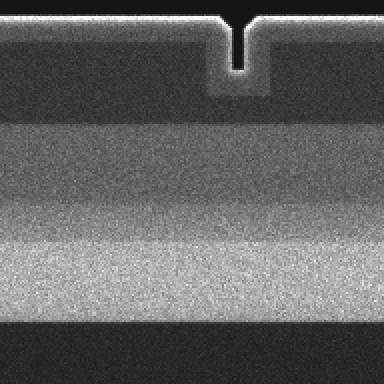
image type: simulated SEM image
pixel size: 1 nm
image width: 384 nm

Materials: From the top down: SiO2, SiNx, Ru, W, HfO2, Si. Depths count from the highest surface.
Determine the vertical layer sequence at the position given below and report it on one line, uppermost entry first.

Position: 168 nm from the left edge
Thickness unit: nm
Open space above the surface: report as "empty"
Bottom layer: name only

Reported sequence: SiO2 26, SiNx 82, Ru 80, W 38, HfO2 80, Si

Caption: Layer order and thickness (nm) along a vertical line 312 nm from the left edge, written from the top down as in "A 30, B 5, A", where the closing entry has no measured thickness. SiO2 26, SiNx 82, Ru 80, W 38, HfO2 80, Si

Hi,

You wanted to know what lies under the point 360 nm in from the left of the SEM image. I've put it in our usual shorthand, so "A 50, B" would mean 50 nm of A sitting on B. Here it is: SiO2 26, SiNx 82, Ru 80, W 38, HfO2 80, Si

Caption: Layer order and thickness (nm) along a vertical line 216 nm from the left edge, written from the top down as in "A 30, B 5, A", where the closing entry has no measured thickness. SiO2 80, SiNx 28, Ru 80, W 38, HfO2 80, Si